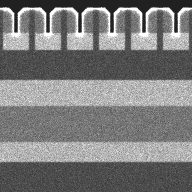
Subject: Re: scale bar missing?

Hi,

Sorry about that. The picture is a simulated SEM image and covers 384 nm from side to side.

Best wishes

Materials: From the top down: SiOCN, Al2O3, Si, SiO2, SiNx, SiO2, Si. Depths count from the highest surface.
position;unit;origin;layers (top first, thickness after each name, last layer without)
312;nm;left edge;SiOCN 50, Al2O3 34, Si 60, SiO2 52, SiNx 72, SiO2 40, Si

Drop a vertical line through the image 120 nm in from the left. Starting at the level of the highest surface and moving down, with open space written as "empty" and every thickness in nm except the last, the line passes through SiOCN 50, Al2O3 34, Si 60, SiO2 52, SiNx 72, SiO2 40, Si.